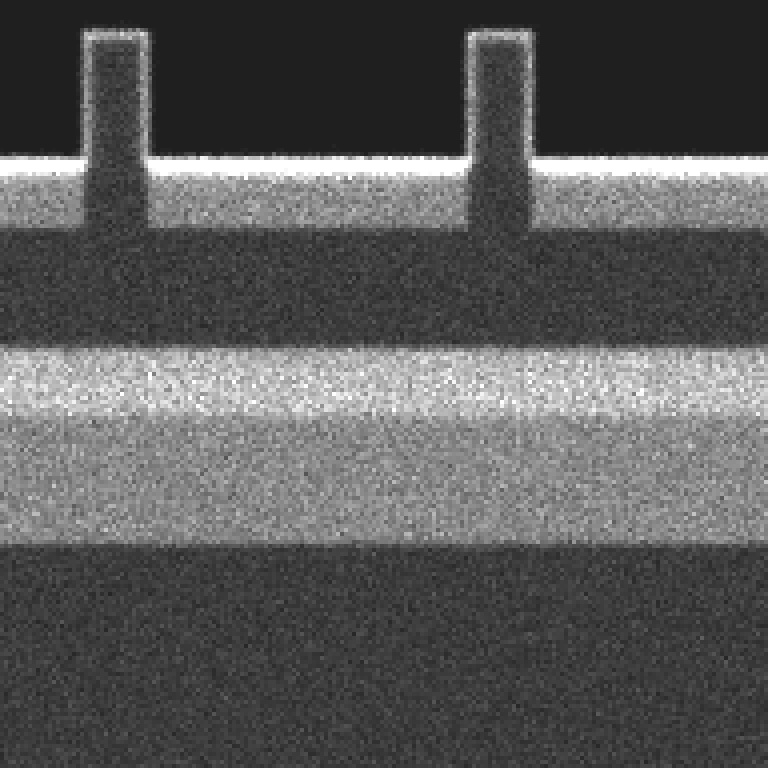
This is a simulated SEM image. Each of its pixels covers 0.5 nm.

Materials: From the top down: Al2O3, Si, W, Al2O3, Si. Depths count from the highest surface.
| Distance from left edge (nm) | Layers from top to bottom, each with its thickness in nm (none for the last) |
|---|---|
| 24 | empty 64, Al2O3 34, Si 60, W 34, Al2O3 64, Si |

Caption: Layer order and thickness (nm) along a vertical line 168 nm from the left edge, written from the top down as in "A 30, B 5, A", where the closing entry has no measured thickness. empty 64, Al2O3 34, Si 60, W 34, Al2O3 64, Si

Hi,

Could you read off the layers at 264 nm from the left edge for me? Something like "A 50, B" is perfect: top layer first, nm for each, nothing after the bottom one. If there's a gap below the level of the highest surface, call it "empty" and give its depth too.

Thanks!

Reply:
Si 158, W 34, Al2O3 64, Si